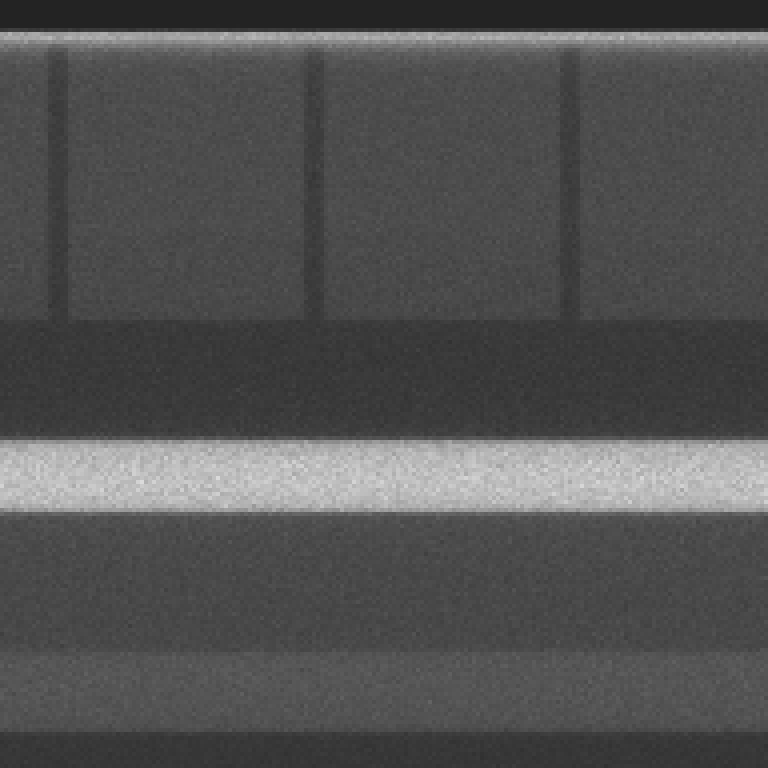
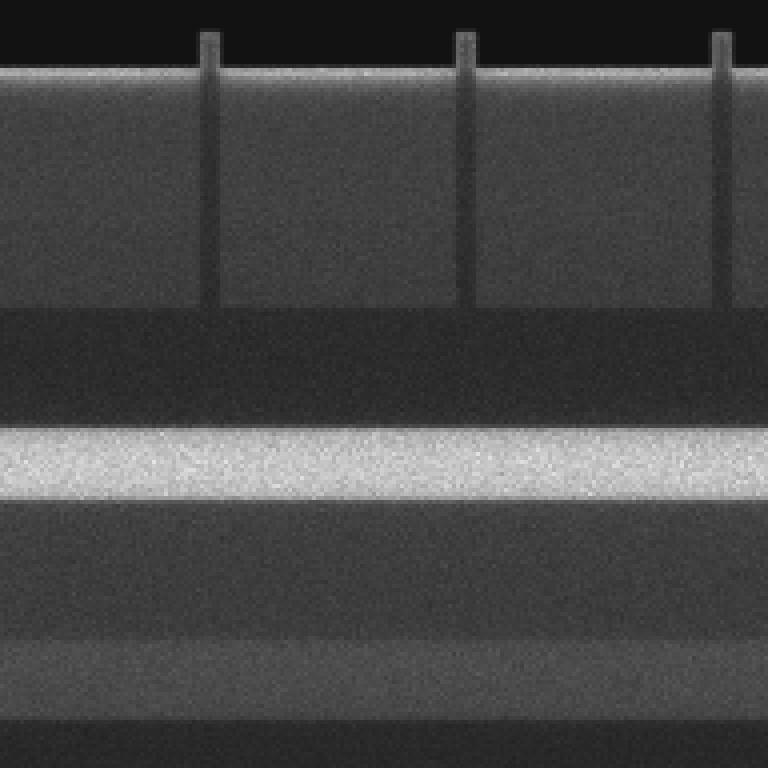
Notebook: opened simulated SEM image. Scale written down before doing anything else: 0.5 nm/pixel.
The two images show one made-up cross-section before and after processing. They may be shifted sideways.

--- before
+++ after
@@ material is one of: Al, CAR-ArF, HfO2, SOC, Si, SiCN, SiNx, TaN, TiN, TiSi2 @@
SOC removed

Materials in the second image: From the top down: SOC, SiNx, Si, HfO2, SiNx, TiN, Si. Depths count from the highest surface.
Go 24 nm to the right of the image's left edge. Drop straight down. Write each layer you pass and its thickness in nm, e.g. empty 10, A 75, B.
empty 18, SOC 76, SiNx 44, Si 60, HfO2 36, SiNx 70, TiN 40, Si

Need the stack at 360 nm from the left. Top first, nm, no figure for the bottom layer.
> Si 198, HfO2 36, SiNx 70, TiN 40, Si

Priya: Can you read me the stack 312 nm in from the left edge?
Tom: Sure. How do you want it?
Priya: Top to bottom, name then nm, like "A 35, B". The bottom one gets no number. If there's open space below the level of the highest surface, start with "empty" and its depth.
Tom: empty 18, SOC 76, SiNx 44, Si 60, HfO2 36, SiNx 70, TiN 40, Si